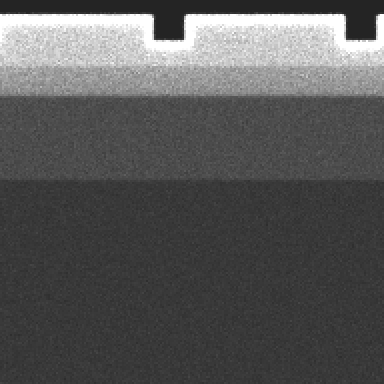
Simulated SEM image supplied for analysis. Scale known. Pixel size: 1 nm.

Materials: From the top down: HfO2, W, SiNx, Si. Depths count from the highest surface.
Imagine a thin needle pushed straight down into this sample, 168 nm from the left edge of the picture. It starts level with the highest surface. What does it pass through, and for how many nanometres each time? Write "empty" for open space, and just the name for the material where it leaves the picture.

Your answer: empty 26, HfO2 24, W 30, SiNx 84, Si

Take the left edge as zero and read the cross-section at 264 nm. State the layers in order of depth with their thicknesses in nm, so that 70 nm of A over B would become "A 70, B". HfO2 50, W 30, SiNx 84, Si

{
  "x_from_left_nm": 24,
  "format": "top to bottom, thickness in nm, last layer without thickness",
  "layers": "HfO2 50, W 30, SiNx 84, Si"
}